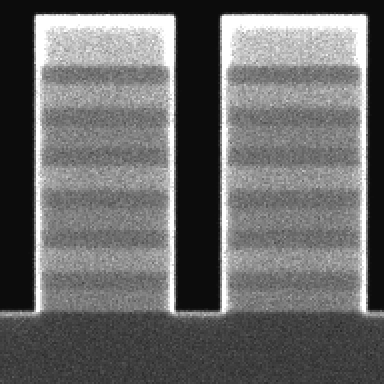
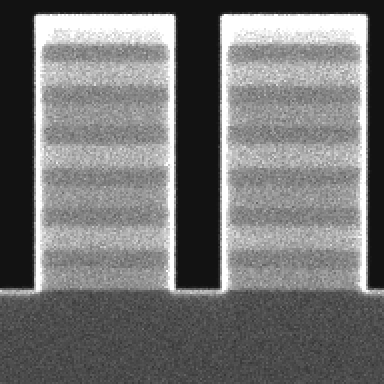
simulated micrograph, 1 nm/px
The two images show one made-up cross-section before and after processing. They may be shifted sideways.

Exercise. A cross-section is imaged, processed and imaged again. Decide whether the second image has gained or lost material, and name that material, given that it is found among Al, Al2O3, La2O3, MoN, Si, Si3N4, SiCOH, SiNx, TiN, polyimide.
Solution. removed: Al2O3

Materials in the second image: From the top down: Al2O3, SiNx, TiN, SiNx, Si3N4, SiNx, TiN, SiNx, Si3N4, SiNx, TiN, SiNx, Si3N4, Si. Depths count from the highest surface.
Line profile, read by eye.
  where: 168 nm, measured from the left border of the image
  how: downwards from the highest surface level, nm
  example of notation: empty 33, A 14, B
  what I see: Al2O3 28, SiNx 18, TiN 24, SiNx 18, Si3N4 22, SiNx 18, TiN 24, SiNx 18, Si3N4 22, SiNx 18, TiN 24, SiNx 18, Si3N4 22, Si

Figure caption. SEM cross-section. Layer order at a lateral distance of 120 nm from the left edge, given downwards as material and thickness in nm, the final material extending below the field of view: Al2O3 28, SiNx 18, TiN 24, SiNx 18, Si3N4 22, SiNx 18, TiN 24, SiNx 18, Si3N4 22, SiNx 18, TiN 24, SiNx 18, Si3N4 22, Si